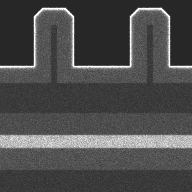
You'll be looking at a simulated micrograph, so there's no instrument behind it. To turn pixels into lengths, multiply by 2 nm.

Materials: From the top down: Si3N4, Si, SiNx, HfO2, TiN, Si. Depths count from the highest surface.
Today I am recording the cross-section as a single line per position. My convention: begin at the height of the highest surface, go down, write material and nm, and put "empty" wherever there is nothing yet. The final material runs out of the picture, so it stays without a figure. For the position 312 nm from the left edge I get Si3N4 150, Si 60, SiNx 44, HfO2 26, TiN 44, Si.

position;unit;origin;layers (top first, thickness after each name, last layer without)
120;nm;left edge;Si3N4 150, Si 60, SiNx 44, HfO2 26, TiN 44, Si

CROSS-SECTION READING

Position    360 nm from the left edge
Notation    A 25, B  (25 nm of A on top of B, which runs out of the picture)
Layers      empty 116, Si3N4 34, Si 60, SiNx 44, HfO2 26, TiN 44, Si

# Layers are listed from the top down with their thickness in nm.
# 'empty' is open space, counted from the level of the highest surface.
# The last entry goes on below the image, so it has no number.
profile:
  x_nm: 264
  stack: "empty 12, Si3N4 138, Si 60, SiNx 44, HfO2 26, TiN 44, Si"